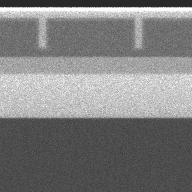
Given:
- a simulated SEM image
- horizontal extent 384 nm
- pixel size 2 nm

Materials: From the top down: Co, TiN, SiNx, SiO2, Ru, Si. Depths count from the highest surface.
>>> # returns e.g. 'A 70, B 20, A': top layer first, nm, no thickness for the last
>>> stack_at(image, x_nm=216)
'Co 20, TiN 6, SiNx 72, SiO2 34, Ru 88, Si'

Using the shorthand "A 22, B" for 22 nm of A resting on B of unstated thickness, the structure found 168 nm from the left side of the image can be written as Co 20, TiN 6, SiNx 72, SiO2 34, Ru 88, Si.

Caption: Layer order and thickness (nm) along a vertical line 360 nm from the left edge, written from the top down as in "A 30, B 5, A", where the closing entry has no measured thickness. Co 20, TiN 6, SiNx 72, SiO2 34, Ru 88, Si